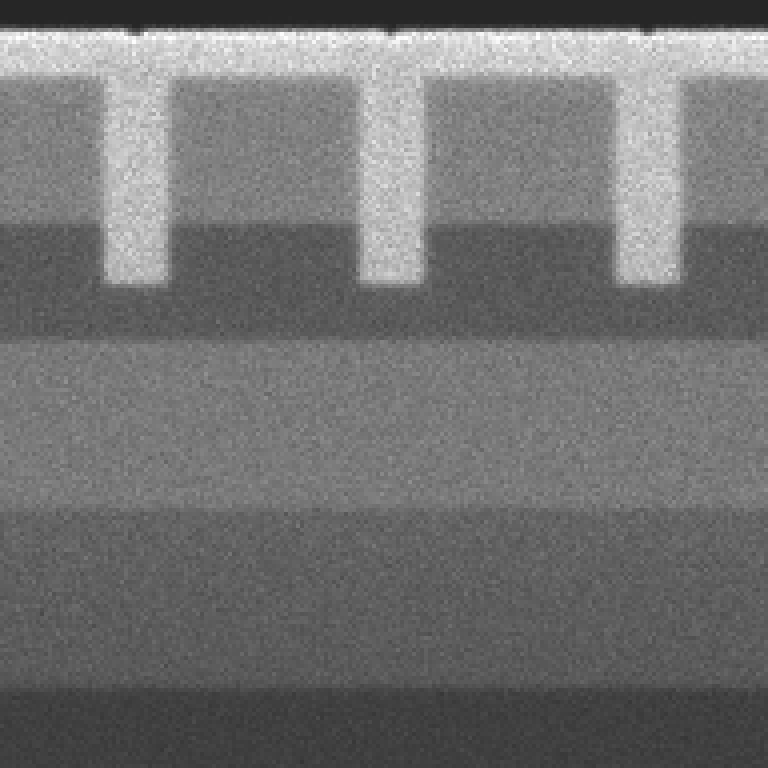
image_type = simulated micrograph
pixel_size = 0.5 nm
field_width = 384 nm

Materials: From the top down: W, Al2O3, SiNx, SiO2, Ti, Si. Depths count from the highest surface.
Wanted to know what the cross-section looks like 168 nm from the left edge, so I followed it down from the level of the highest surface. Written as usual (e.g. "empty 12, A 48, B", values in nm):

W 22, Al2O3 74, SiNx 58, SiO2 84, Ti 90, Si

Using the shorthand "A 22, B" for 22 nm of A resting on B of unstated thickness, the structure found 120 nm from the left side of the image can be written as W 22, Al2O3 74, SiNx 58, SiO2 84, Ti 90, Si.